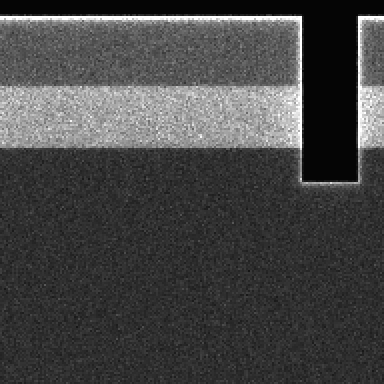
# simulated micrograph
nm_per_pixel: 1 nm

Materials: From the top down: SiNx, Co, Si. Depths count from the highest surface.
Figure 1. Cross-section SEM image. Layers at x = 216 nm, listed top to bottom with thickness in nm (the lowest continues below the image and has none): SiNx 70, Co 62, Si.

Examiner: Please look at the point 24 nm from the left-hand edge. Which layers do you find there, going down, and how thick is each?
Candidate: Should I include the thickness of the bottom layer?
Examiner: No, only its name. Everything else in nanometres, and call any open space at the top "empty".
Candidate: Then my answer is SiNx 70, Co 62, Si